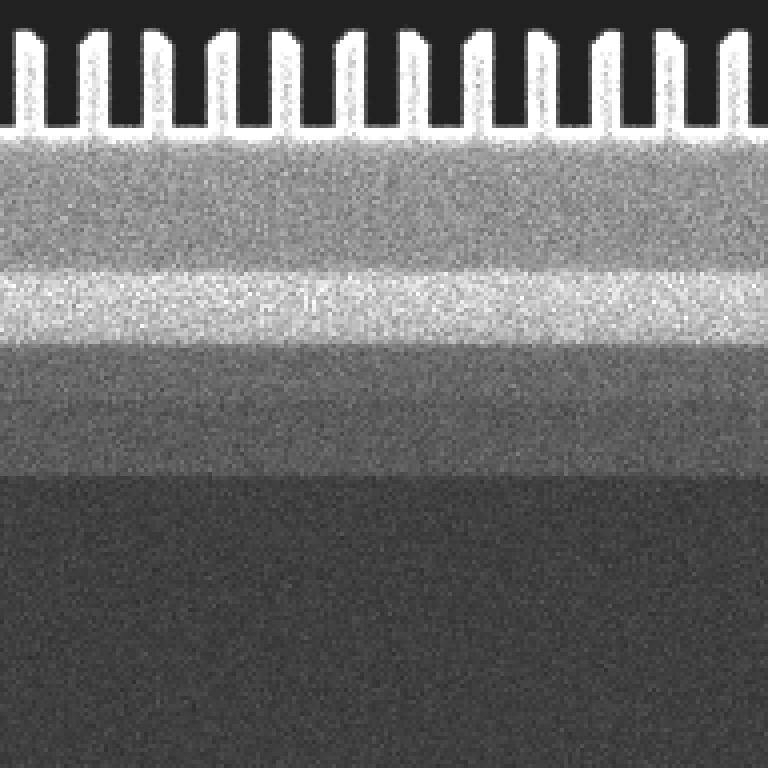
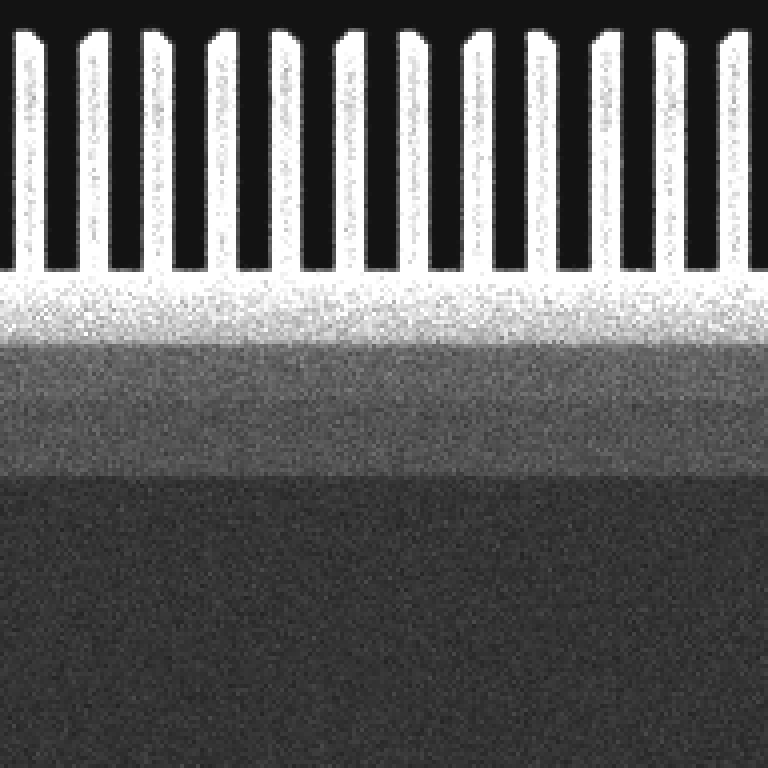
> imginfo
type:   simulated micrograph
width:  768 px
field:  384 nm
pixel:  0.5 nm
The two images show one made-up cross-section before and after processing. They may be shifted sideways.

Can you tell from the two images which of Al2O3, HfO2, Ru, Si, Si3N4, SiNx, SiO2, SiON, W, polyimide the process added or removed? Yes, it removed Al2O3.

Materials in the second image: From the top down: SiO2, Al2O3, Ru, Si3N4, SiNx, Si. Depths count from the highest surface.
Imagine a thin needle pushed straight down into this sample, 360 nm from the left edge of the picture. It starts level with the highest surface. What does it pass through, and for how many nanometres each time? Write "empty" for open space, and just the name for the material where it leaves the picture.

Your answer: empty 6, SiO2 42, Al2O3 72, Ru 36, Si3N4 28, SiNx 38, Si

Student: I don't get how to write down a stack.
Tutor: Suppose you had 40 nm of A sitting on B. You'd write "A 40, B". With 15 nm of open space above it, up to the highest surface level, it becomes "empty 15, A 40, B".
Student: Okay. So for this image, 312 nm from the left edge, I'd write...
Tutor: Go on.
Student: empty 120, Ru 36, Si3N4 28, SiNx 38, Si